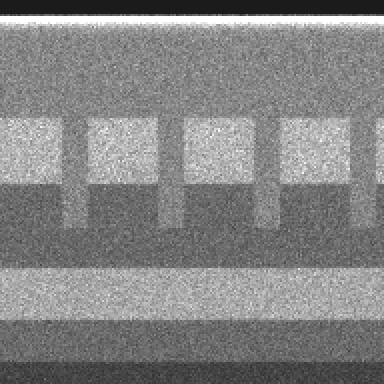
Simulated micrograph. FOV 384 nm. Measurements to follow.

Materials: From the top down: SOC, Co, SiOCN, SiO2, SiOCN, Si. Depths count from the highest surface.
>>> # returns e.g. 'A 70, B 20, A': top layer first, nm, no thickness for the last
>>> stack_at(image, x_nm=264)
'SOC 212, SiOCN 40, SiO2 52, SiOCN 42, Si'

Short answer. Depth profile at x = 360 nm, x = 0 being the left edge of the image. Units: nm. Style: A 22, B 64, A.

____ SOC 212, SiOCN 40, SiO2 52, SiOCN 42, Si